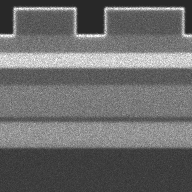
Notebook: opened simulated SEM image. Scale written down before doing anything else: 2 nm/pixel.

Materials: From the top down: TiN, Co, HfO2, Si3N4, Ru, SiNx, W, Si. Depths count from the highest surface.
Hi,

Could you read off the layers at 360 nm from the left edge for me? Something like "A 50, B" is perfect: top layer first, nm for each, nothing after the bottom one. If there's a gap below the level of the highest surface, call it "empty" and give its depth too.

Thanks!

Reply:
TiN 54, Co 36, HfO2 30, Si3N4 34, Ru 64, SiNx 10, W 52, Si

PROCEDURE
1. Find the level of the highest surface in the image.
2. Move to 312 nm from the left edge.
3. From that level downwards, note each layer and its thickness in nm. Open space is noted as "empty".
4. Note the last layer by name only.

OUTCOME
TiN 54, Co 36, HfO2 30, Si3N4 34, Ru 64, SiNx 10, W 52, Si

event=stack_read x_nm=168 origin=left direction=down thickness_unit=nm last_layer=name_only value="empty 54, Co 36, HfO2 30, Si3N4 34, Ru 64, SiNx 10, W 52, Si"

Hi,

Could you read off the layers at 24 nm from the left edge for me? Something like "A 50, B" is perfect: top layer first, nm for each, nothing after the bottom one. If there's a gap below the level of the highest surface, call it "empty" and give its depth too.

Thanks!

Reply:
empty 54, Co 36, HfO2 30, Si3N4 34, Ru 64, SiNx 10, W 52, Si